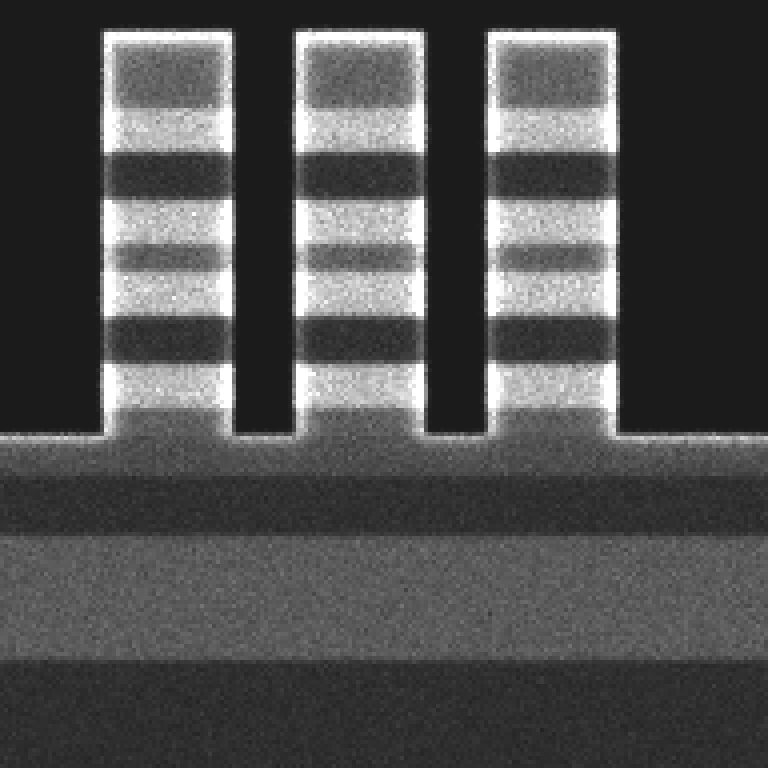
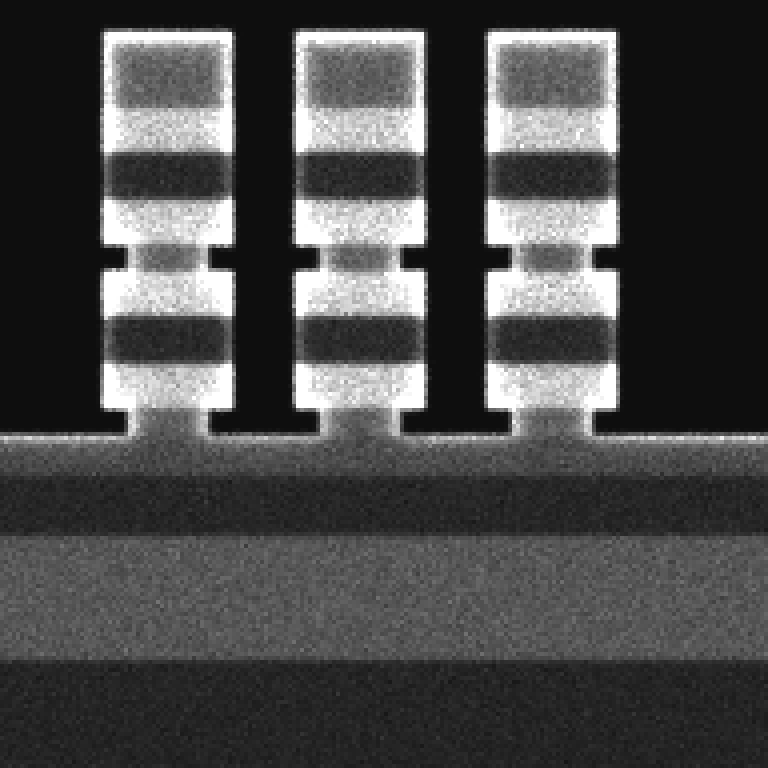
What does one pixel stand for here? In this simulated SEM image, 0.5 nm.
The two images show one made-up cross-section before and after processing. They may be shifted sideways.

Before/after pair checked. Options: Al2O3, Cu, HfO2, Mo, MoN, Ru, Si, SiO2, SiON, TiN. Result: removed SiO2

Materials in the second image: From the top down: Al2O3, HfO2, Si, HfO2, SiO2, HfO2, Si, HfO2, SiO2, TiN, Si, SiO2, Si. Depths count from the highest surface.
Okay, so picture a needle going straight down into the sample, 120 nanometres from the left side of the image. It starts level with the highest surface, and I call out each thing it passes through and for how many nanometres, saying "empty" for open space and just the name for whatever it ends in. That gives empty 202, TiN 20, Si 30, SiO2 62, Si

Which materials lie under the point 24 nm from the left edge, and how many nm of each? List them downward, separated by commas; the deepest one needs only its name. empty 202, TiN 20, Si 30, SiO2 62, Si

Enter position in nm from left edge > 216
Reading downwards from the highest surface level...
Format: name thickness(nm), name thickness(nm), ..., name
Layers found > empty 202, TiN 20, Si 30, SiO2 62, Si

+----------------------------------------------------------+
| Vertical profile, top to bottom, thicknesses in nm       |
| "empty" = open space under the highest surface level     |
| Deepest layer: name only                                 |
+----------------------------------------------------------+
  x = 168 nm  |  Al2O3 38, HfO2 22, Si 24, HfO2 22, SiO2 14, HfO2 22, Si 24, HfO2 22, SiO2 14, TiN 20, Si 30, SiO2 62, Si